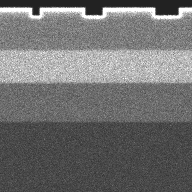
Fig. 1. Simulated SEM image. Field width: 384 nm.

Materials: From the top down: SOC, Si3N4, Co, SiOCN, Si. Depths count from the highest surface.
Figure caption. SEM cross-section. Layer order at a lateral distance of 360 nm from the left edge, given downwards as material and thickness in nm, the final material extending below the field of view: SOC 16, Si3N4 68, Co 66, SiOCN 78, Si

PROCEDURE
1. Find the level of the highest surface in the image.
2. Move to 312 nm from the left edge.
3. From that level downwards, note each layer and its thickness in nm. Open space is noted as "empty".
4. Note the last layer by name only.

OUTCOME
empty 16, Si3N4 68, Co 66, SiOCN 78, Si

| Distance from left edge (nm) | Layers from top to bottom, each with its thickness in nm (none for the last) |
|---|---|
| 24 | SOC 16, Si3N4 68, Co 66, SiOCN 78, Si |